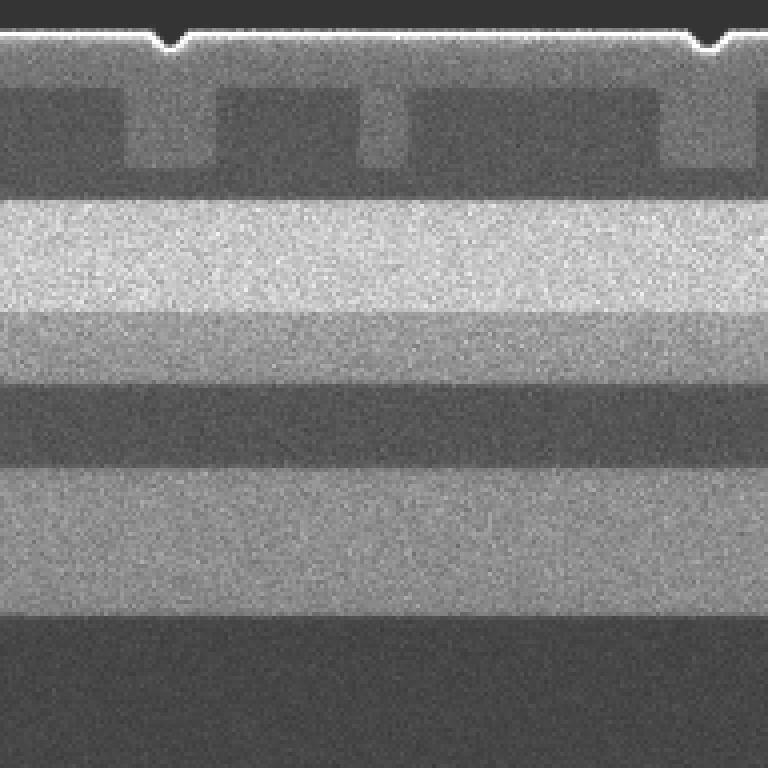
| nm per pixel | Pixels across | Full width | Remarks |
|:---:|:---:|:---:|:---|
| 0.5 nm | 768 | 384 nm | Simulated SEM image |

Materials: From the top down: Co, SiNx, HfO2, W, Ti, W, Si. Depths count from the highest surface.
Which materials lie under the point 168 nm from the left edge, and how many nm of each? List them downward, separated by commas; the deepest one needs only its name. Co 28, SiNx 56, HfO2 56, W 36, Ti 42, W 74, Si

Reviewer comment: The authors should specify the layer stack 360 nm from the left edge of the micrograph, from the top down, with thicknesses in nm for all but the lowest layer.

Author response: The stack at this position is empty 4, Co 64, SiNx 16, HfO2 56, W 36, Ti 42, W 74, Si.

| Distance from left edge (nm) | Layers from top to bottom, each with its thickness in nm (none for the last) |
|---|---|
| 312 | Co 28, SiNx 56, HfO2 56, W 36, Ti 42, W 74, Si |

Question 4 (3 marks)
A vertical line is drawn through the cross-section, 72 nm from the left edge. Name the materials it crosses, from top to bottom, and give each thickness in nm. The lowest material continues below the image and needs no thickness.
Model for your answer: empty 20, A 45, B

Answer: Co 68, SiNx 16, HfO2 56, W 36, Ti 42, W 74, Si